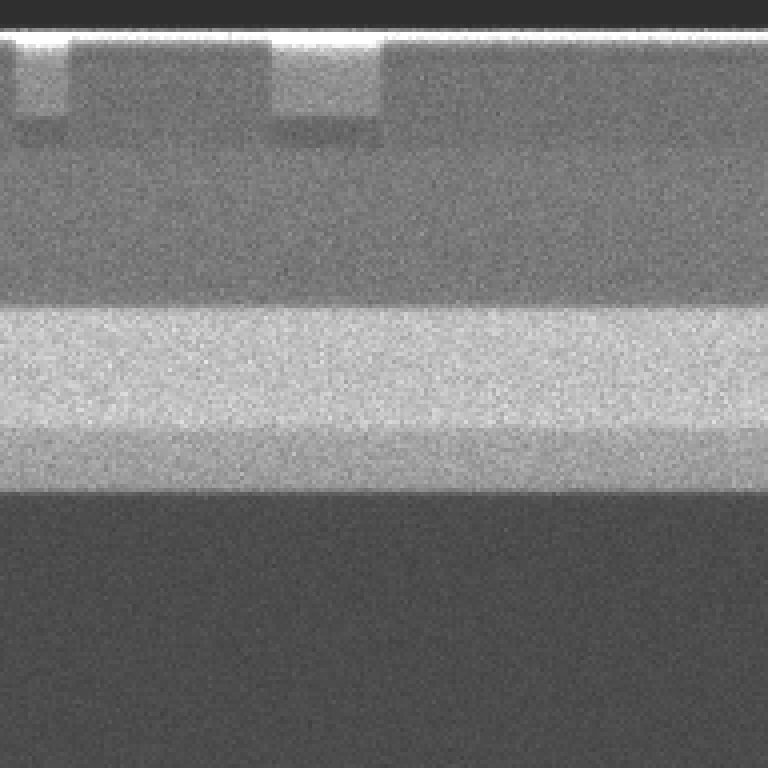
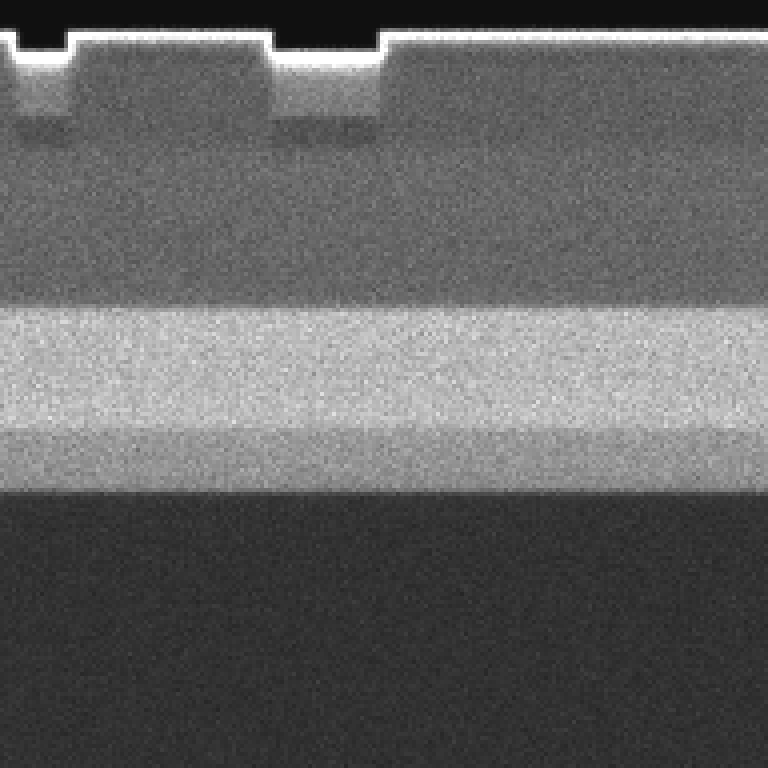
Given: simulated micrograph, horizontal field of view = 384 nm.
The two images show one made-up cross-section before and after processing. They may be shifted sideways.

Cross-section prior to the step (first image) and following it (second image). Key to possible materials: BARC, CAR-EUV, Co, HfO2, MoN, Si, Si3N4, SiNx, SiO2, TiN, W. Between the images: SiO2 was removed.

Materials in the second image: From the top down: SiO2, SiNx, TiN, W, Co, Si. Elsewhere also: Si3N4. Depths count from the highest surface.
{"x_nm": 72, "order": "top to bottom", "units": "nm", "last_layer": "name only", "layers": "SiNx 16, Si3N4 42, TiN 80, W 60, Co 32, Si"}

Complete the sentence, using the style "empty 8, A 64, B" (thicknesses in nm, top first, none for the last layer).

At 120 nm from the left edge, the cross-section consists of SiNx 16, Si3N4 42, TiN 80, W 60, Co 32, Si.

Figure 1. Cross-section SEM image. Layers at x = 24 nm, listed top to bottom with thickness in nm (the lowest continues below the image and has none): empty 10, SiO2 32, SiNx 16, TiN 80, W 60, Co 32, Si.